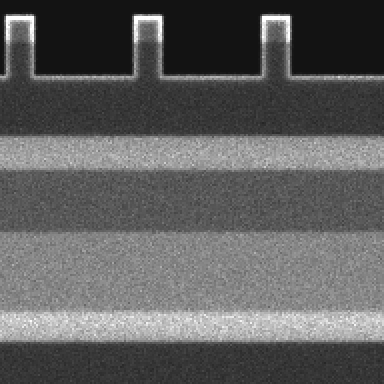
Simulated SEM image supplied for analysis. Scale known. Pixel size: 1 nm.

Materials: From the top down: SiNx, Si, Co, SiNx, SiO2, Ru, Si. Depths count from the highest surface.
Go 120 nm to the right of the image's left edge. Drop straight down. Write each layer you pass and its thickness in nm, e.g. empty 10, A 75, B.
empty 60, Si 60, Co 34, SiNx 62, SiO2 80, Ru 30, Si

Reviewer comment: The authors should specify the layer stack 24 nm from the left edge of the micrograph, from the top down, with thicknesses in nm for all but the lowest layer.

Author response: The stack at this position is SiNx 26, Si 94, Co 34, SiNx 62, SiO2 80, Ru 30, Si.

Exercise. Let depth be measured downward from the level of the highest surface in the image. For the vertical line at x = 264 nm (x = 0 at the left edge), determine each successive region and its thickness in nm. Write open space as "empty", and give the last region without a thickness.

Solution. SiNx 26, Si 94, Co 34, SiNx 62, SiO2 80, Ru 30, Si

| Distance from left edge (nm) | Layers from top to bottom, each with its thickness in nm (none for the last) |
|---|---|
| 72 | empty 60, Si 60, Co 34, SiNx 62, SiO2 80, Ru 30, Si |